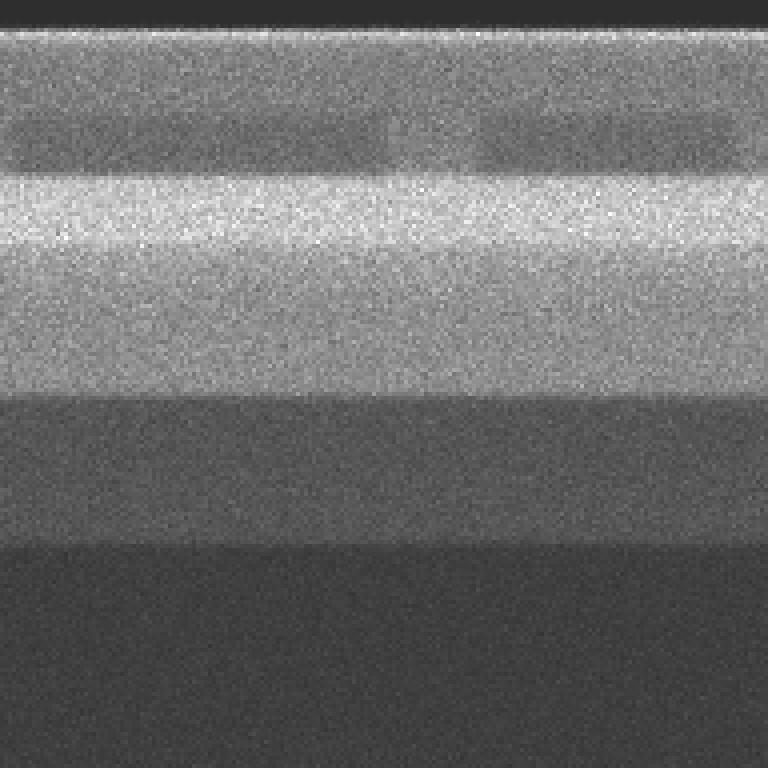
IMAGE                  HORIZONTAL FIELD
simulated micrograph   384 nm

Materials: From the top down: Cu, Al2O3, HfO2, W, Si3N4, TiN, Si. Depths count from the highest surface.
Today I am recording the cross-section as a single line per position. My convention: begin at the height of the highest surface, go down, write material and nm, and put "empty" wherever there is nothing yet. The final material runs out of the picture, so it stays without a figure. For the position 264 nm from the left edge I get Cu 42, Al2O3 30, HfO2 34, W 76, Si3N4 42, TiN 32, Si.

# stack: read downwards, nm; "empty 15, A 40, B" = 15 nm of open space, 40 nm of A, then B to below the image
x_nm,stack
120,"Cu 42, Al2O3 30, HfO2 34, W 76, Si3N4 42, TiN 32, Si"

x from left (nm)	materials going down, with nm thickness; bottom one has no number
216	Cu 72, HfO2 34, W 76, Si3N4 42, TiN 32, Si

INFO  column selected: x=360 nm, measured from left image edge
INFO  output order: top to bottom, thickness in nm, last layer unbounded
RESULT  Cu 42, Al2O3 30, HfO2 34, W 76, Si3N4 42, TiN 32, Si